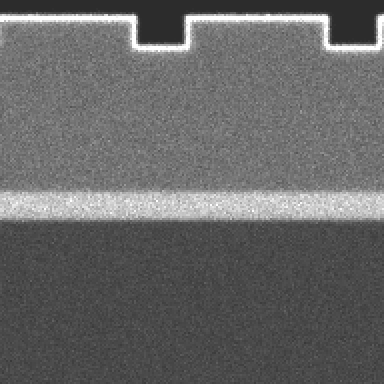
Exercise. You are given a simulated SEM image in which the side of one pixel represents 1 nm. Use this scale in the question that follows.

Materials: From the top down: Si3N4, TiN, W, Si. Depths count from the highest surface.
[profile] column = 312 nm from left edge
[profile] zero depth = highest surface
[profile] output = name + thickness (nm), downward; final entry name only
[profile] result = Si3N4 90, TiN 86, W 28, Si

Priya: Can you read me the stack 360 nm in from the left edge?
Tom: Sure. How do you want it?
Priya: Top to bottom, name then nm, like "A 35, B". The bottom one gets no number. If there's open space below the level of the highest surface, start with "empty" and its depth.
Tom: empty 30, Si3N4 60, TiN 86, W 28, Si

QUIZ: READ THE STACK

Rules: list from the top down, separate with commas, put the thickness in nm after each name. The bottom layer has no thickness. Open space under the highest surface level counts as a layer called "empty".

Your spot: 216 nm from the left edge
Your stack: Si3N4 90, TiN 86, W 28, Si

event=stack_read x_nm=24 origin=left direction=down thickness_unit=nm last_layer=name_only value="Si3N4 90, TiN 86, W 28, Si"